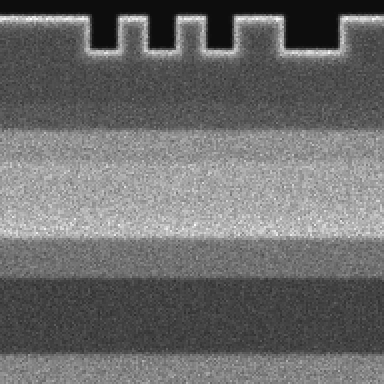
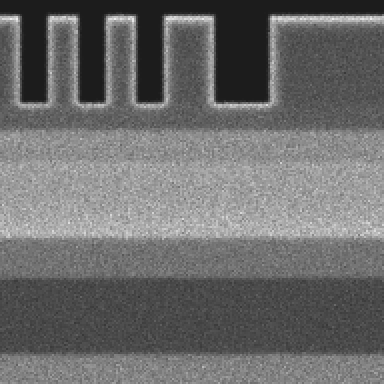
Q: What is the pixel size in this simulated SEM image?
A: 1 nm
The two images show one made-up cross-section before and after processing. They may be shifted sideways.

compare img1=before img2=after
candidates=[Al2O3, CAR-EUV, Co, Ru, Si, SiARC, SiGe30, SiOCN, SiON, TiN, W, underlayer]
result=removed:underlayer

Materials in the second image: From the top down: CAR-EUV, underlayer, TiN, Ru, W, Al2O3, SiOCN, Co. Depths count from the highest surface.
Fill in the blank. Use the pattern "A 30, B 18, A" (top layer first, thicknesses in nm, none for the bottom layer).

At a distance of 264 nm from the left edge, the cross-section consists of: empty 88, TiN 26, Ru 32, W 76, Al2O3 40, SiOCN 76, Co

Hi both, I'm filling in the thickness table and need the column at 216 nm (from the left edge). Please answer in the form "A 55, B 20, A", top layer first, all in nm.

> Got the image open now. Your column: empty 88, TiN 26, Ru 32, W 76, Al2O3 40, SiOCN 76, Co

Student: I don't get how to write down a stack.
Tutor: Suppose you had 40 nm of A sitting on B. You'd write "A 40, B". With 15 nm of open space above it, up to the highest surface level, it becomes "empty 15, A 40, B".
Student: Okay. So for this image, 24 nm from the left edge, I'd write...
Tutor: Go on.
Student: empty 88, TiN 26, Ru 32, W 76, Al2O3 40, SiOCN 76, Co